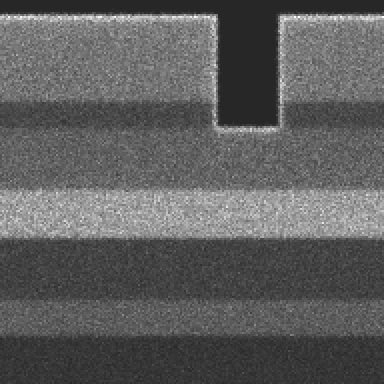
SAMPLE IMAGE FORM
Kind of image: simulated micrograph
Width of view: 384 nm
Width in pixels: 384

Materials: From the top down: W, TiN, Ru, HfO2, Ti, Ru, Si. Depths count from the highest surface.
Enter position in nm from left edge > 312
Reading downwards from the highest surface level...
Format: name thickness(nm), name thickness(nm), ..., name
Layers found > W 86, TiN 26, Ru 62, HfO2 48, Ti 62, Ru 36, Si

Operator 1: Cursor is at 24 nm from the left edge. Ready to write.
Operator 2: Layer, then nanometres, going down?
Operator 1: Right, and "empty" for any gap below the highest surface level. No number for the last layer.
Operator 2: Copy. W 86, TiN 26, Ru 62, HfO2 48, Ti 62, Ru 36, Si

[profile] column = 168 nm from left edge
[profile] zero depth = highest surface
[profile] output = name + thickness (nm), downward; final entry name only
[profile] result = W 86, TiN 26, Ru 62, HfO2 48, Ti 62, Ru 36, Si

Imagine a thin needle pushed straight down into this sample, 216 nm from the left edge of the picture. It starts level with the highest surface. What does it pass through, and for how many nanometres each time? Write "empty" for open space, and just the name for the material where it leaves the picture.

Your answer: empty 112, Ru 62, HfO2 48, Ti 62, Ru 36, Si